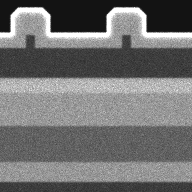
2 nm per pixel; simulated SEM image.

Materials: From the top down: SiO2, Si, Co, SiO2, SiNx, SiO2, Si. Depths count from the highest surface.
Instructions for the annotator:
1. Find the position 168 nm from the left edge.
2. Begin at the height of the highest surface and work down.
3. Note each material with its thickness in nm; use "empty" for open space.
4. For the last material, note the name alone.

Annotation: empty 50, SiO2 30, Si 60, Co 30, SiO2 66, SiNx 72, SiO2 40, Si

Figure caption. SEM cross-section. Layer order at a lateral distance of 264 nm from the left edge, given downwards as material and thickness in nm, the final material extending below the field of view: SiO2 80, Si 60, Co 30, SiO2 66, SiNx 72, SiO2 40, Si